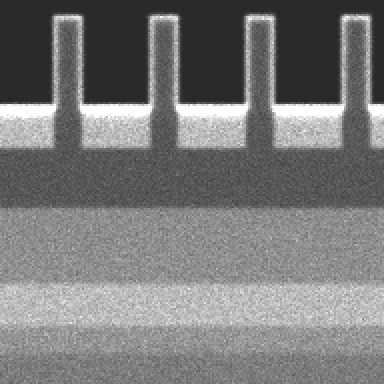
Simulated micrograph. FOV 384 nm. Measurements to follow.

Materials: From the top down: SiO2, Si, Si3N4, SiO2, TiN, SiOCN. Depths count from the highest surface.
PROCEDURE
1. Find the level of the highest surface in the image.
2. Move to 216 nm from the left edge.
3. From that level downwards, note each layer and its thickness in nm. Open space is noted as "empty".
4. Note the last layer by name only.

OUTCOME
empty 90, SiO2 42, Si 60, Si3N4 76, SiO2 42, TiN 28, SiOCN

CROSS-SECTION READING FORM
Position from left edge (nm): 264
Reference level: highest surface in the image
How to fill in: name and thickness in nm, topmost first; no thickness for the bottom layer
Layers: Si 192, Si3N4 76, SiO2 42, TiN 28, SiOCN